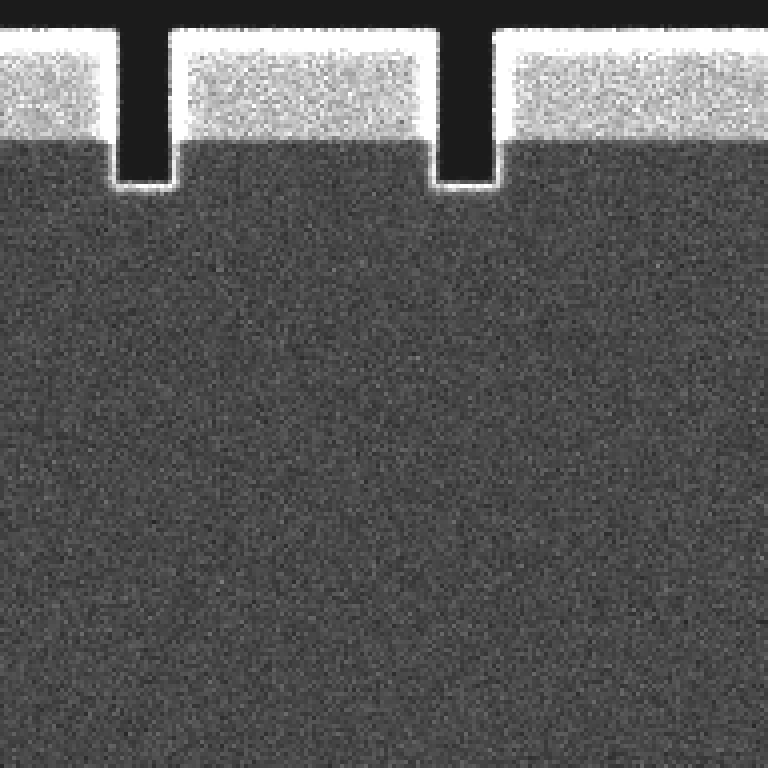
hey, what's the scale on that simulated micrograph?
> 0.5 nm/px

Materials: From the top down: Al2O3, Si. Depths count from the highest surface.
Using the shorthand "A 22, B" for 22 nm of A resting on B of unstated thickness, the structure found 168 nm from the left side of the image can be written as Al2O3 54, Si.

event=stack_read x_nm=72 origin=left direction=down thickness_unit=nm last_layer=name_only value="empty 76, Si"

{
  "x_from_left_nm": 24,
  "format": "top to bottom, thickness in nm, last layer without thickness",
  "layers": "Al2O3 54, Si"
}